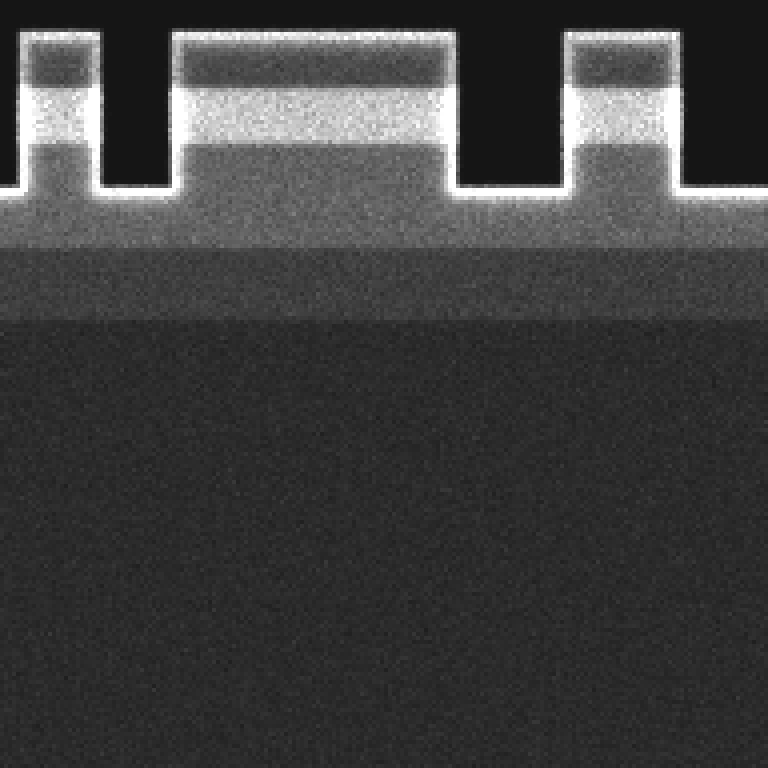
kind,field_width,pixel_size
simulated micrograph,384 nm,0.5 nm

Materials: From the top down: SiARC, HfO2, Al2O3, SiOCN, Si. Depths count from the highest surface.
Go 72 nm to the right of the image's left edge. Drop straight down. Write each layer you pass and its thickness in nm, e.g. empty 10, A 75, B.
empty 78, Al2O3 30, SiOCN 36, Si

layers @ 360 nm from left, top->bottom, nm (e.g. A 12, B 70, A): empty 78, Al2O3 30, SiOCN 36, Si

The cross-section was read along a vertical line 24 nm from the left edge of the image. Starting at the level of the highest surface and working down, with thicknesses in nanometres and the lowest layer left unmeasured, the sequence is SiARC 28, HfO2 28, Al2O3 52, SiOCN 36, Si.